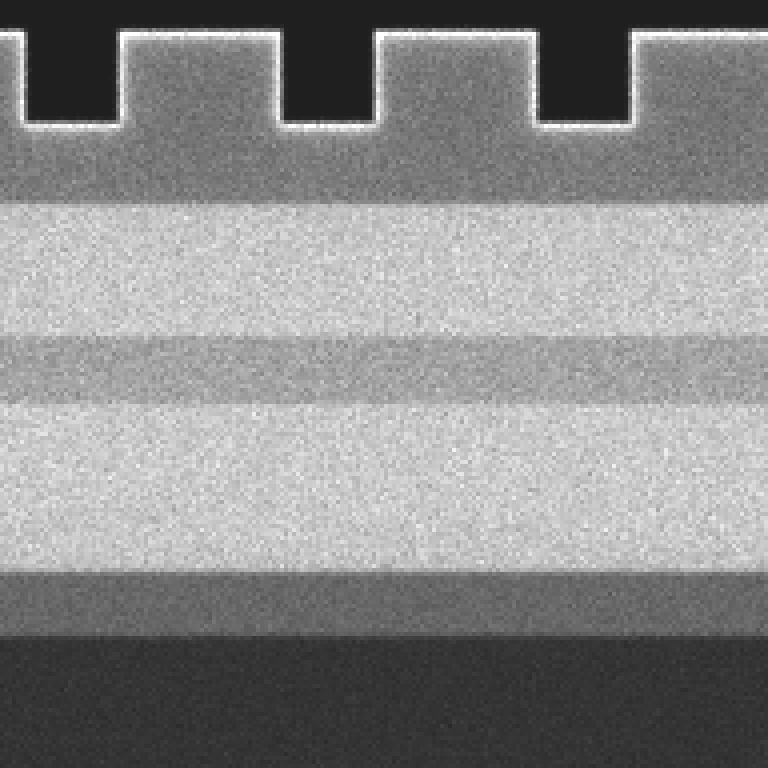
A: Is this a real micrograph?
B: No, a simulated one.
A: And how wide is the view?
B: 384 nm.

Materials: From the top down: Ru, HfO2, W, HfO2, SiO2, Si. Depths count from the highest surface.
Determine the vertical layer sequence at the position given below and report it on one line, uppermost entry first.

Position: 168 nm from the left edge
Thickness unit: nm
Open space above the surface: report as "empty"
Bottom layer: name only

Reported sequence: empty 46, Ru 40, HfO2 66, W 34, HfO2 84, SiO2 32, Si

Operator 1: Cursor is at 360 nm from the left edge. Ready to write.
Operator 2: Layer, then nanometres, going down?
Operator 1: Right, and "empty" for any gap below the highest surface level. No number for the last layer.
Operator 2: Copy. Ru 86, HfO2 66, W 34, HfO2 84, SiO2 32, Si